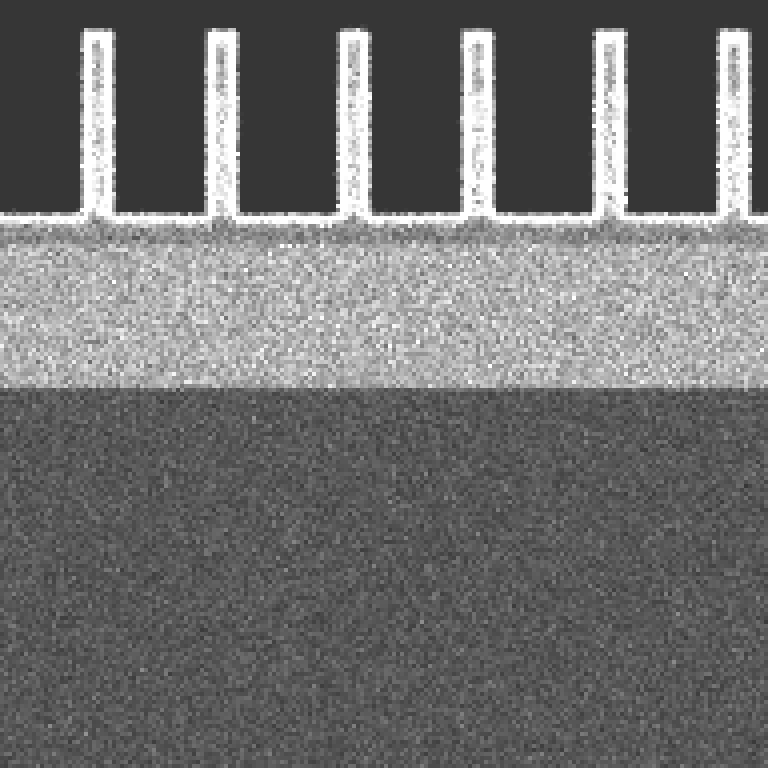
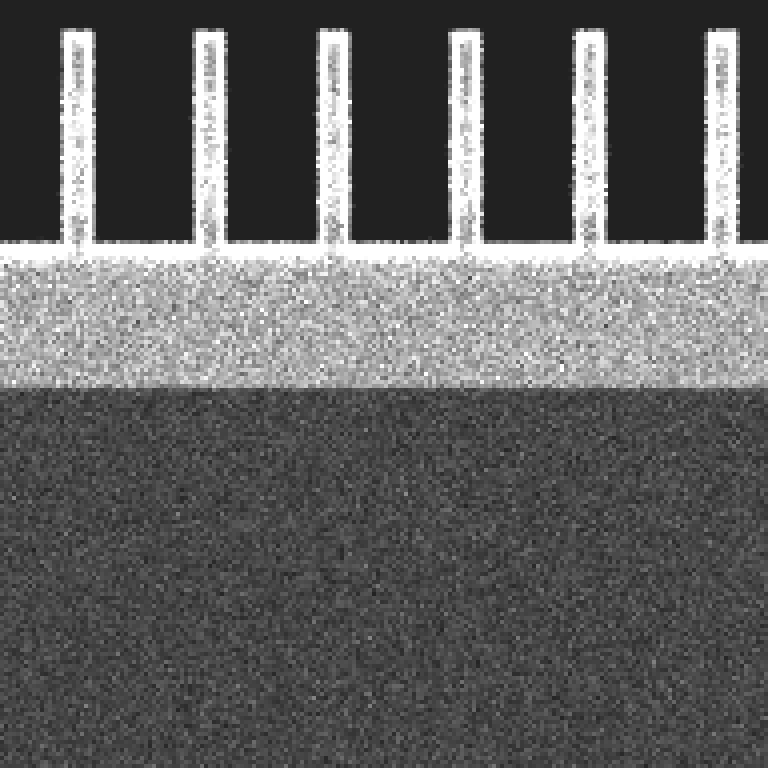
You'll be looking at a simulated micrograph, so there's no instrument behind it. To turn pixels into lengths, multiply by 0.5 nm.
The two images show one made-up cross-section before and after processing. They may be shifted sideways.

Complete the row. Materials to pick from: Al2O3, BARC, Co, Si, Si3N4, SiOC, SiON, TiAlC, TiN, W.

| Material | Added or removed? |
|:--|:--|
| TiN | removed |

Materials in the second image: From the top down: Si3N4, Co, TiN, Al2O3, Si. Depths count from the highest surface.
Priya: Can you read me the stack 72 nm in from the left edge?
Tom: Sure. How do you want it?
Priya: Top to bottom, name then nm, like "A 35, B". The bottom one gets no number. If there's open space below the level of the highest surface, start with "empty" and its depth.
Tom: empty 106, Al2O3 72, Si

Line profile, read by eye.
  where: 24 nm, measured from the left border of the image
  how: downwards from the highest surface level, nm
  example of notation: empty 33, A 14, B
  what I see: empty 106, Al2O3 72, Si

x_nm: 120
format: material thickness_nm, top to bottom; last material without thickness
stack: empty 106, Al2O3 72, Si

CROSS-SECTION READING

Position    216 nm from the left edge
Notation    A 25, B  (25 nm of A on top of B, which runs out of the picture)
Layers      empty 106, Al2O3 72, Si